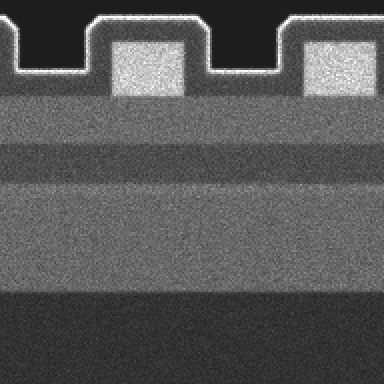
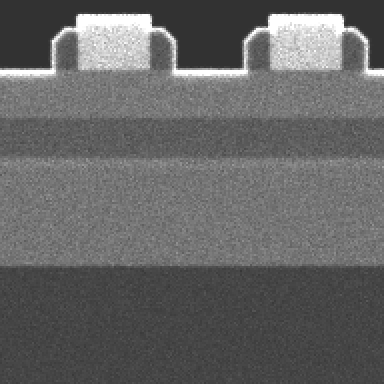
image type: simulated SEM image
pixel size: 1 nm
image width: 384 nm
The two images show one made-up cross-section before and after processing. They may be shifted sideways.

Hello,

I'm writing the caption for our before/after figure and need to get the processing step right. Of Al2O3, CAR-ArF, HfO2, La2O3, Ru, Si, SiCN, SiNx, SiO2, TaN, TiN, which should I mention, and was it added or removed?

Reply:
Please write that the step removed SiNx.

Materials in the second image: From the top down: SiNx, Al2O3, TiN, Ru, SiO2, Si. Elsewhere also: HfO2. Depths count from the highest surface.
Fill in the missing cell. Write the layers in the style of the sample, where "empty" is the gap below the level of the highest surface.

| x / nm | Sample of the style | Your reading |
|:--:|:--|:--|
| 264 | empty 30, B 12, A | empty 12, SiNx 42, Al2O3 48, TiN 40, Ru 10, SiO2 98, Si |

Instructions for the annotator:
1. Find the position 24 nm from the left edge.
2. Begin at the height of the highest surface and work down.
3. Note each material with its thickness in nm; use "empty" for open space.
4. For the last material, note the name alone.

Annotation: empty 54, Al2O3 48, TiN 40, Ru 10, SiO2 98, Si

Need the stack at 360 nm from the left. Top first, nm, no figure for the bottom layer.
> empty 18, SiNx 36, Al2O3 48, TiN 40, Ru 10, SiO2 98, Si